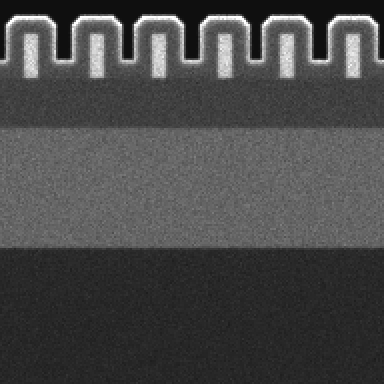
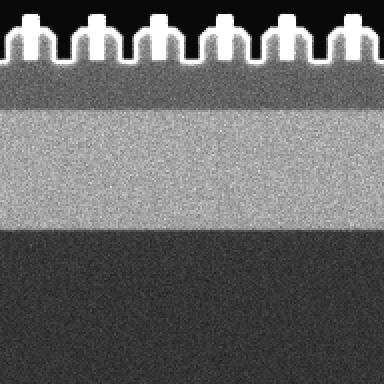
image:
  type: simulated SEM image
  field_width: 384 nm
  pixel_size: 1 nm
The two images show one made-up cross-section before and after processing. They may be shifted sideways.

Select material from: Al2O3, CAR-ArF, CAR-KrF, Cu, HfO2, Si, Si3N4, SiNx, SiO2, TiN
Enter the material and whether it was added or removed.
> Si3N4 / removed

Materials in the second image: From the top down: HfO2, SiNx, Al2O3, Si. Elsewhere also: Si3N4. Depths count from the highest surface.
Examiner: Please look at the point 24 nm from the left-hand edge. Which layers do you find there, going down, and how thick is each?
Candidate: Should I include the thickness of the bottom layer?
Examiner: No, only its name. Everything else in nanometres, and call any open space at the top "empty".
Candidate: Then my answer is HfO2 44, SiNx 50, Al2O3 120, Si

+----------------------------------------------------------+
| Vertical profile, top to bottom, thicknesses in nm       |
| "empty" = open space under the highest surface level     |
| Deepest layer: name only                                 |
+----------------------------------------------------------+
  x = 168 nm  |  empty 12, Si3N4 32, SiNx 50, Al2O3 120, Si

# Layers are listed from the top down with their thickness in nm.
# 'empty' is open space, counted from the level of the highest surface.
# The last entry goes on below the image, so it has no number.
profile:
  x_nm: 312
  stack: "empty 44, SiNx 50, Al2O3 120, Si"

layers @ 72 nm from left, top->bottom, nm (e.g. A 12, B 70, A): empty 20, Si3N4 24, SiNx 50, Al2O3 120, Si